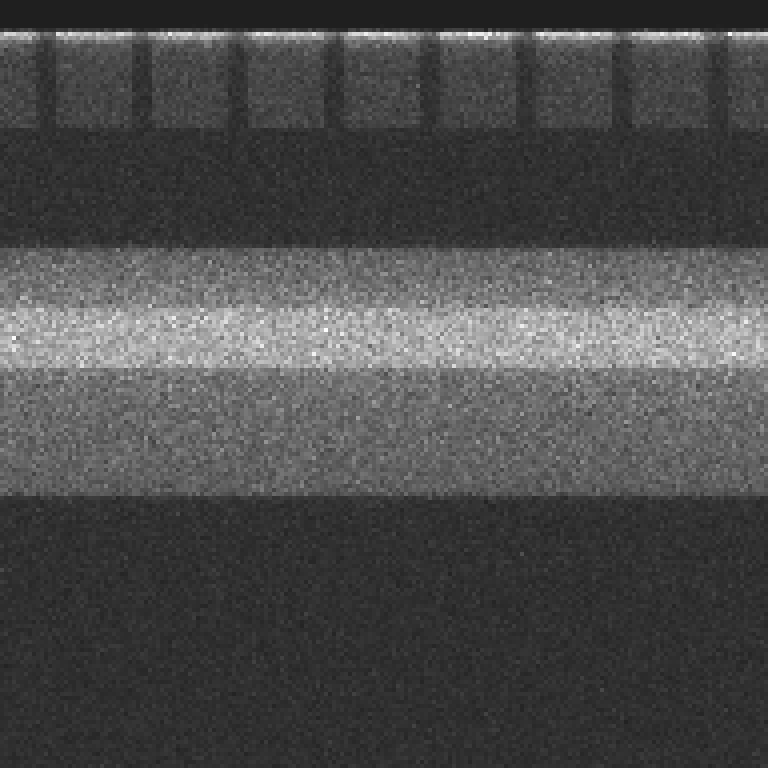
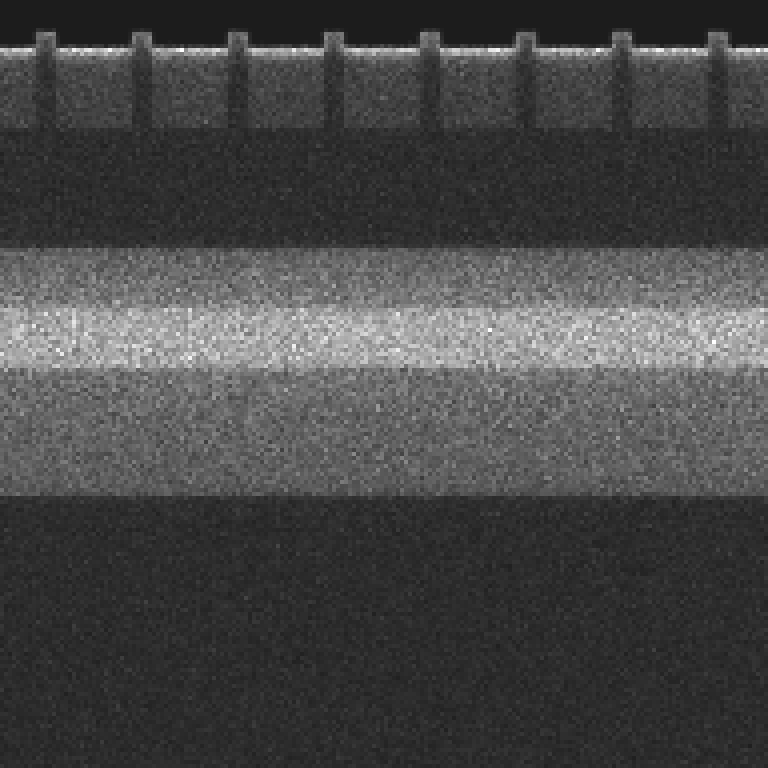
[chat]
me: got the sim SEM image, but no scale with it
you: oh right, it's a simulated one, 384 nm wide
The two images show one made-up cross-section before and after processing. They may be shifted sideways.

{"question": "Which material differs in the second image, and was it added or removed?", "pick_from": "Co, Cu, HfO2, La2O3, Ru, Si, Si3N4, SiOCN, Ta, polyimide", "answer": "Si3N4, removed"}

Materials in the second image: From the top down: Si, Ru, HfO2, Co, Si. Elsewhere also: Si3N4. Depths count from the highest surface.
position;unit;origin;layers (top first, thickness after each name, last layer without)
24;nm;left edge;Si 108, Ru 30, HfO2 30, Co 64, Si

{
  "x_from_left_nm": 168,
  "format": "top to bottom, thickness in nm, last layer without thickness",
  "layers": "Si 108, Ru 30, HfO2 30, Co 64, Si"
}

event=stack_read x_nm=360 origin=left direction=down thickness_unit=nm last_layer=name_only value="Si 108, Ru 30, HfO2 30, Co 64, Si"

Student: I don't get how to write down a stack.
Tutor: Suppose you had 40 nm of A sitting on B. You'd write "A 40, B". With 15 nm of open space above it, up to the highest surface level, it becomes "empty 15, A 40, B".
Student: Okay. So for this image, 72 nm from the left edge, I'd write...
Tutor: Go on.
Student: Si 108, Ru 30, HfO2 30, Co 64, Si